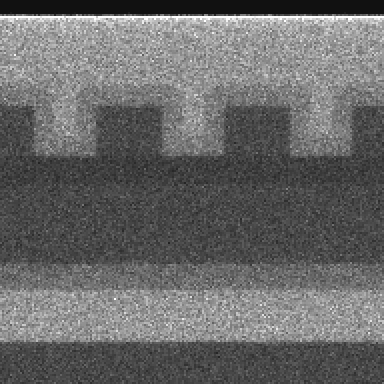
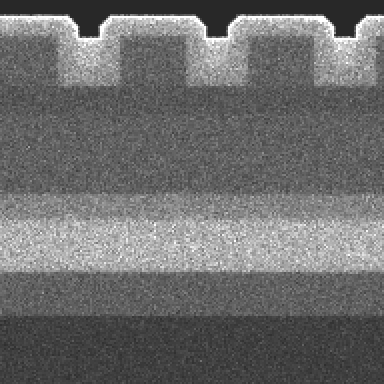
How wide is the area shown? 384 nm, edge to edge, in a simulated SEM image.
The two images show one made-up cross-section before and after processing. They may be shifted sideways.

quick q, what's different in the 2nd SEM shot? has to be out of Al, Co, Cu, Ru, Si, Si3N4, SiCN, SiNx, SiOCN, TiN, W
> W removed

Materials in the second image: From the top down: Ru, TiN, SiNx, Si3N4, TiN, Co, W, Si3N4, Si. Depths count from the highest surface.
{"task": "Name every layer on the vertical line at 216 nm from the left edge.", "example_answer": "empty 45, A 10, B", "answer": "empty 22, W 28, Ru 20, SiNx 28, Si3N4 16, TiN 64, Co 26, W 52, Si3N4 44, Si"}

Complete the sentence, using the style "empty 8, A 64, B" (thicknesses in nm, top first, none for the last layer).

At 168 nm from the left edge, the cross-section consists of Ru 20, TiN 50, SiNx 28, Si3N4 16, TiN 64, Co 26, W 52, Si3N4 44, Si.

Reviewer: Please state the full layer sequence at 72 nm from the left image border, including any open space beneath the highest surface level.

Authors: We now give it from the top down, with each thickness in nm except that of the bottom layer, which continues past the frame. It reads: empty 6, Ru 64, SiNx 28, Si3N4 16, TiN 64, Co 26, W 52, Si3N4 44, Si